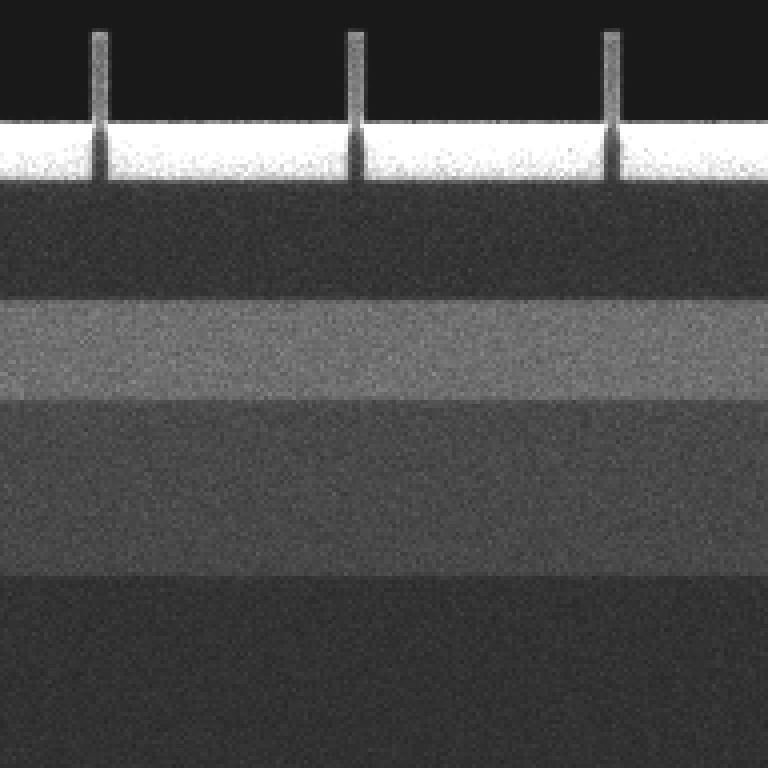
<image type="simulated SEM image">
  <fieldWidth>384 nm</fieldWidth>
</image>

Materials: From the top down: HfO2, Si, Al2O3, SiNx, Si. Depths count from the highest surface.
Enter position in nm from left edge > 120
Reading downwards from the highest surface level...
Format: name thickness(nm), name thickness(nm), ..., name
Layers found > empty 46, HfO2 28, Si 60, Al2O3 50, SiNx 88, Si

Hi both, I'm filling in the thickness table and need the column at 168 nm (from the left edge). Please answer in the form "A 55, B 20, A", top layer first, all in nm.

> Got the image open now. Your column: empty 46, HfO2 28, Si 60, Al2O3 50, SiNx 88, Si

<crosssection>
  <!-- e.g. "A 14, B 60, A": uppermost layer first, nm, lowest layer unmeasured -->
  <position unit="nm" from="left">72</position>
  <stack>empty 46, HfO2 28, Si 60, Al2O3 50, SiNx 88, Si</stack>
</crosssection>